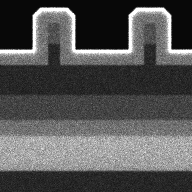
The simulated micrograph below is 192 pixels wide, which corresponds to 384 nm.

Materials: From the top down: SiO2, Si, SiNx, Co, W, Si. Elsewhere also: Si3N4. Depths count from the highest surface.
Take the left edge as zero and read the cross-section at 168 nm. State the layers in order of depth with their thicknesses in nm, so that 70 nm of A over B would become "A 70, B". empty 84, SiO2 30, Si 60, SiNx 50, Co 32, W 70, Si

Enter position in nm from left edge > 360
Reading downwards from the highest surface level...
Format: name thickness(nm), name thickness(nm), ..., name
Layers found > empty 84, SiO2 30, Si 60, SiNx 50, Co 32, W 70, Si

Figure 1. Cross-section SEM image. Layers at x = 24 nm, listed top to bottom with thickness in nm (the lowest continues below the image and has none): empty 84, SiO2 30, Si 60, SiNx 50, Co 32, W 70, Si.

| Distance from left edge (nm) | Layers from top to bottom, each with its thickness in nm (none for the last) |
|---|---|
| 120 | SiO2 114, Si 60, SiNx 50, Co 32, W 70, Si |